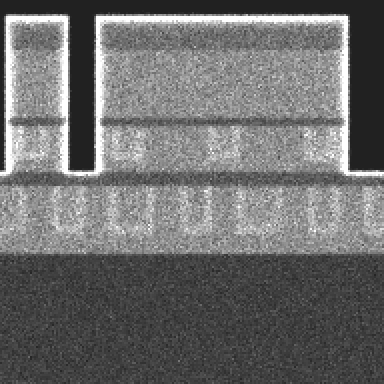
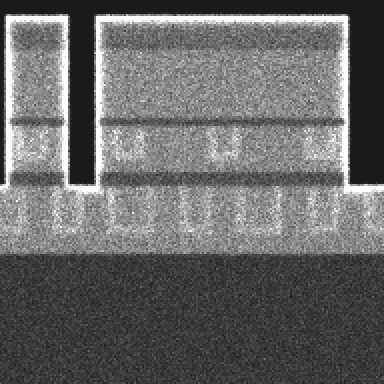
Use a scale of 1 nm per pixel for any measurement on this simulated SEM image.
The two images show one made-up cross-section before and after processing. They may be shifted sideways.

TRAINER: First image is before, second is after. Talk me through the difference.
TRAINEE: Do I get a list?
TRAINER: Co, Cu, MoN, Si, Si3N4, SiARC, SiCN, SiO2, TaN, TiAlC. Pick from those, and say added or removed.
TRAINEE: removed: SiCN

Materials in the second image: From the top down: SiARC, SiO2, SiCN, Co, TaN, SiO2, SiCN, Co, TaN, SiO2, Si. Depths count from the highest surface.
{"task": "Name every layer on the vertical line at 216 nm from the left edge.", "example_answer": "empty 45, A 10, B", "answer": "SiARC 34, SiO2 68, SiCN 8, Co 26, TaN 8, SiO2 12, SiCN 14, SiO2 68, Si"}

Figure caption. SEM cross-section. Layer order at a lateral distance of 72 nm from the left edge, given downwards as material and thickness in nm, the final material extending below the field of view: empty 170, Co 40, TaN 8, SiO2 20, Si